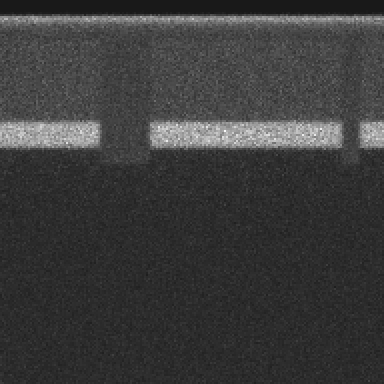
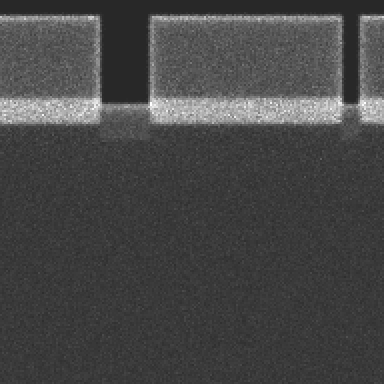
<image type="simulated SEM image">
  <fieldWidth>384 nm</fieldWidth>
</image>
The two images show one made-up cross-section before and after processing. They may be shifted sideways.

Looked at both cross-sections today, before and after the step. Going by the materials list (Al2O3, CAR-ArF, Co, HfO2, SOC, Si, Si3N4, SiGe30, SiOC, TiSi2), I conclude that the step removed SOC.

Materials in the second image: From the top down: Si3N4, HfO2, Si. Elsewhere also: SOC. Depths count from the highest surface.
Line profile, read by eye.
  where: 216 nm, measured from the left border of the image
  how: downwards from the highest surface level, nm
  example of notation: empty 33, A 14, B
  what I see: Si3N4 82, HfO2 26, Si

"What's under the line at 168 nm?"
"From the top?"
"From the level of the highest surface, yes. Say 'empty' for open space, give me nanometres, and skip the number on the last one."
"Si3N4 82, HfO2 26, Si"